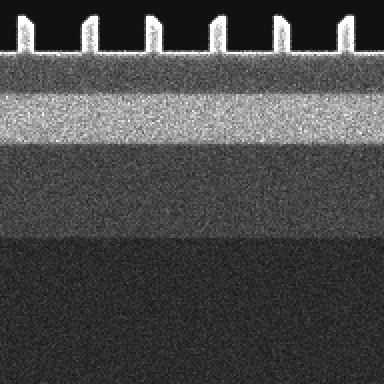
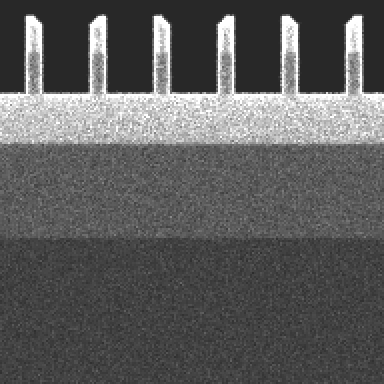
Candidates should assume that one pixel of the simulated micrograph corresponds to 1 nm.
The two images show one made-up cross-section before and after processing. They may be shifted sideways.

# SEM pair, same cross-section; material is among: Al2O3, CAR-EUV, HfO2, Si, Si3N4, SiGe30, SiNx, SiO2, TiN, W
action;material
removed;TiN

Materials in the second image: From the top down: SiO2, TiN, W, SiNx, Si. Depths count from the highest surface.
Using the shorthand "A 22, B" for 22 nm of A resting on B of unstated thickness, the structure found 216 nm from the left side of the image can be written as empty 78, W 50, SiNx 94, Si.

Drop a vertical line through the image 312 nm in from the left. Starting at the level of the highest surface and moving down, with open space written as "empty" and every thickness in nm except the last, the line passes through empty 78, W 50, SiNx 94, Si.